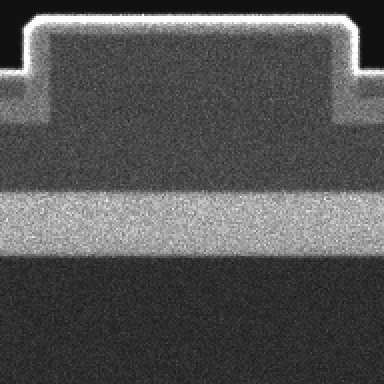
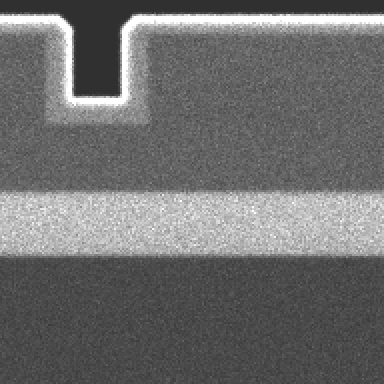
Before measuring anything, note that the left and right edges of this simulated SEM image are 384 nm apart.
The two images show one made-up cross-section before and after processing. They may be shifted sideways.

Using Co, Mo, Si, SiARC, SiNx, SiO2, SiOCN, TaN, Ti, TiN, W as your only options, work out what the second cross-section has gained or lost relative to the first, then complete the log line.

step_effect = removed SiARC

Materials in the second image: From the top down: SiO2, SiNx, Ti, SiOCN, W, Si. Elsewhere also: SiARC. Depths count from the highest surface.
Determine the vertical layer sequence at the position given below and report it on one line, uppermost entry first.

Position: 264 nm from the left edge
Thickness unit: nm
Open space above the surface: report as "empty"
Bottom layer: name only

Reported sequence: SiO2 18, SiNx 48, Ti 42, SiOCN 68, W 64, Si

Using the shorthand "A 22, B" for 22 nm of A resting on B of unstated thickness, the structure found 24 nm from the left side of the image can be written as SiO2 18, SiNx 48, Ti 42, SiOCN 68, W 64, Si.